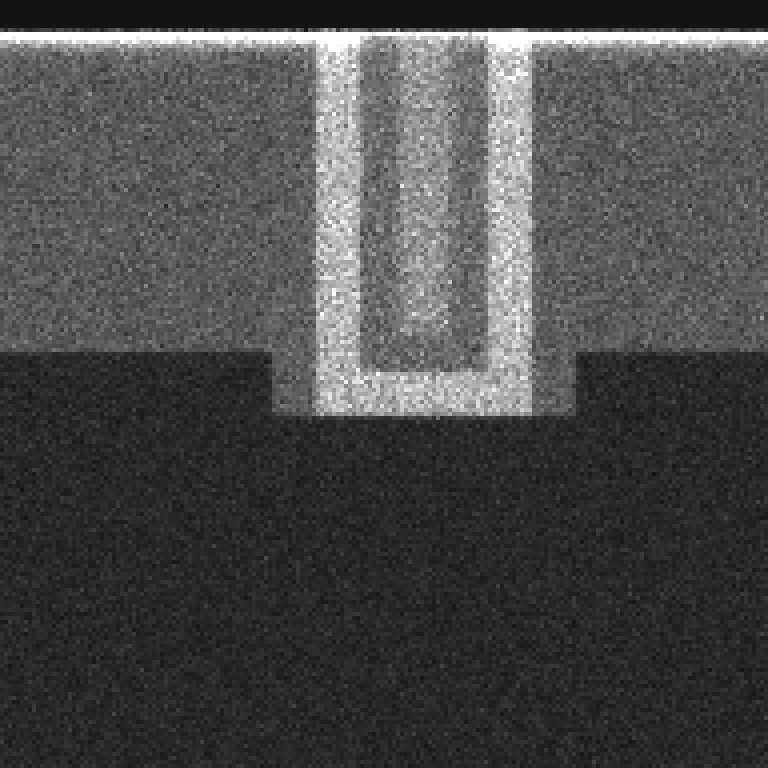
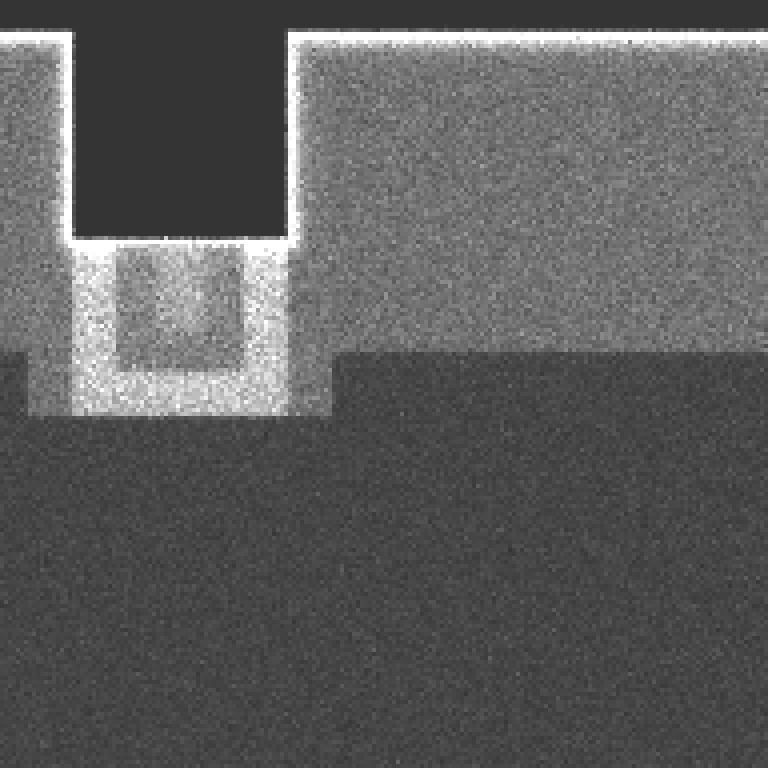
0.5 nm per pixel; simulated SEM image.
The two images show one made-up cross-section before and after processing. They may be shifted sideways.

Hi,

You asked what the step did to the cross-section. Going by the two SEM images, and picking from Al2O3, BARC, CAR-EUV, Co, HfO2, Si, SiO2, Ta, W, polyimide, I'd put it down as Co and HfO2 and W, removed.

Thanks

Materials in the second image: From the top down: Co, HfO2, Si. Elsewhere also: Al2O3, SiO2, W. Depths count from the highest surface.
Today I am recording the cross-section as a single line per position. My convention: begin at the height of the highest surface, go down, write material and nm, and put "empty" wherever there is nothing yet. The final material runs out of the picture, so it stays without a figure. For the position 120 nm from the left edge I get empty 104, Co 66, HfO2 22, Si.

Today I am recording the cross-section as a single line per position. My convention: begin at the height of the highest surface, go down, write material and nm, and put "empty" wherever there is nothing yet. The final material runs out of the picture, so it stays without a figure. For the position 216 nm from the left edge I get SiO2 160, Si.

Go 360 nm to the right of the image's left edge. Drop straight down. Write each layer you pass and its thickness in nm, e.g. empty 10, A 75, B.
SiO2 160, Si